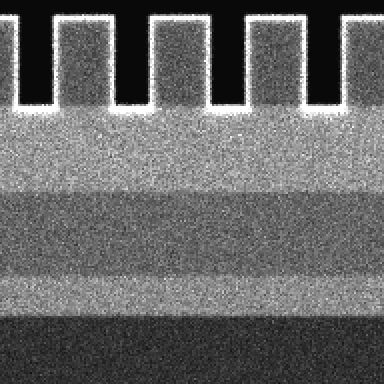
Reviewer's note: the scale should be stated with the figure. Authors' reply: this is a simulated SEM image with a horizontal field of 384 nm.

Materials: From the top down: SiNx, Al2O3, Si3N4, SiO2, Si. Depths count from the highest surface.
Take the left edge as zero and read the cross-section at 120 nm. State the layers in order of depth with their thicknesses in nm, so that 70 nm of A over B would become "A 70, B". empty 90, Al2O3 86, Si3N4 84, SiO2 40, Si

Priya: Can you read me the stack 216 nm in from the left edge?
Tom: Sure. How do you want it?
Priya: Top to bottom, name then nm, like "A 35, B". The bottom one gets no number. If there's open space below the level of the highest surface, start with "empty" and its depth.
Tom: empty 90, Al2O3 86, Si3N4 84, SiO2 40, Si